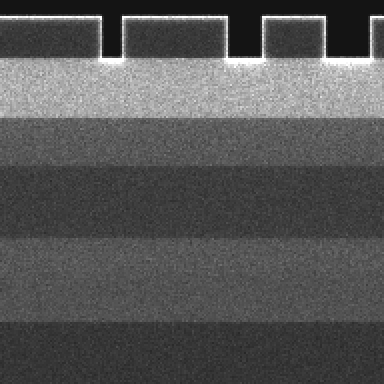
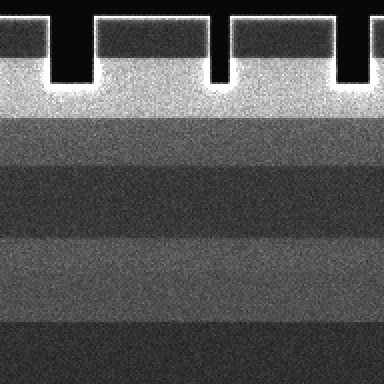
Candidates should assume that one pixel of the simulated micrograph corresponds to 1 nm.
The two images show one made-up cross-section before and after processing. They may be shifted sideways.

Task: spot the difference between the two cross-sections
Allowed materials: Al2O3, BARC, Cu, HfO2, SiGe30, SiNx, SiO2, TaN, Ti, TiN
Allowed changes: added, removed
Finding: removed HfO2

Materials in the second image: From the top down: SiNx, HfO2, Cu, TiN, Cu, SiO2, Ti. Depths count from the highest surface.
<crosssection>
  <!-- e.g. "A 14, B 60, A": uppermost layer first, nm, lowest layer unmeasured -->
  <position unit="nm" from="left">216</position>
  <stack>empty 68, HfO2 34, Cu 48, TiN 72, Cu 34, SiO2 50, Ti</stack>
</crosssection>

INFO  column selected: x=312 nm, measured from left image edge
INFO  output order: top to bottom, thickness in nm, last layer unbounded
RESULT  SiNx 42, HfO2 60, Cu 48, TiN 72, Cu 34, SiO2 50, Ti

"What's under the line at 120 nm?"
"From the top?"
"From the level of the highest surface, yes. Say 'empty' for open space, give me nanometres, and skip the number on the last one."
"SiNx 42, HfO2 60, Cu 48, TiN 72, Cu 34, SiO2 50, Ti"